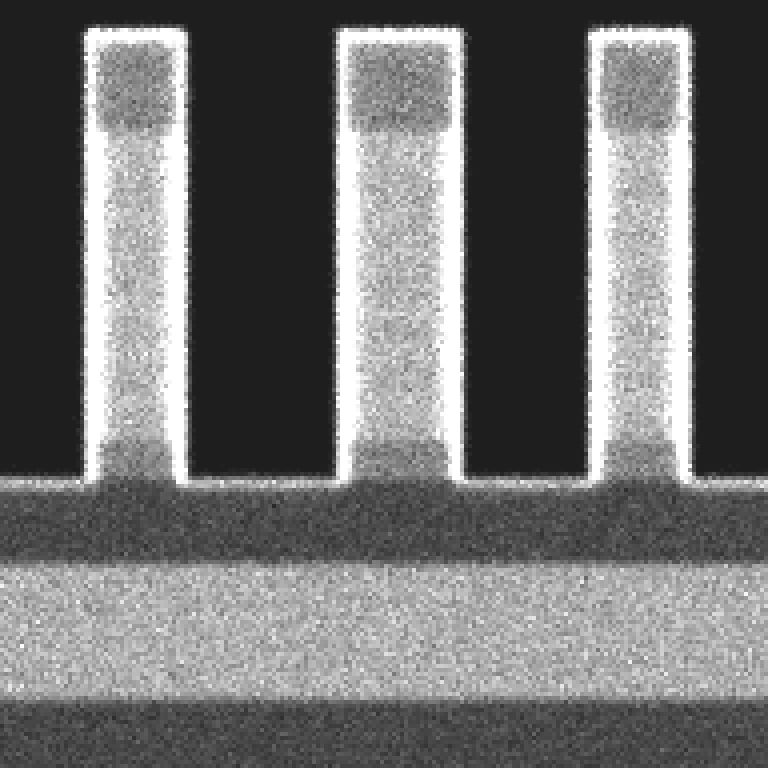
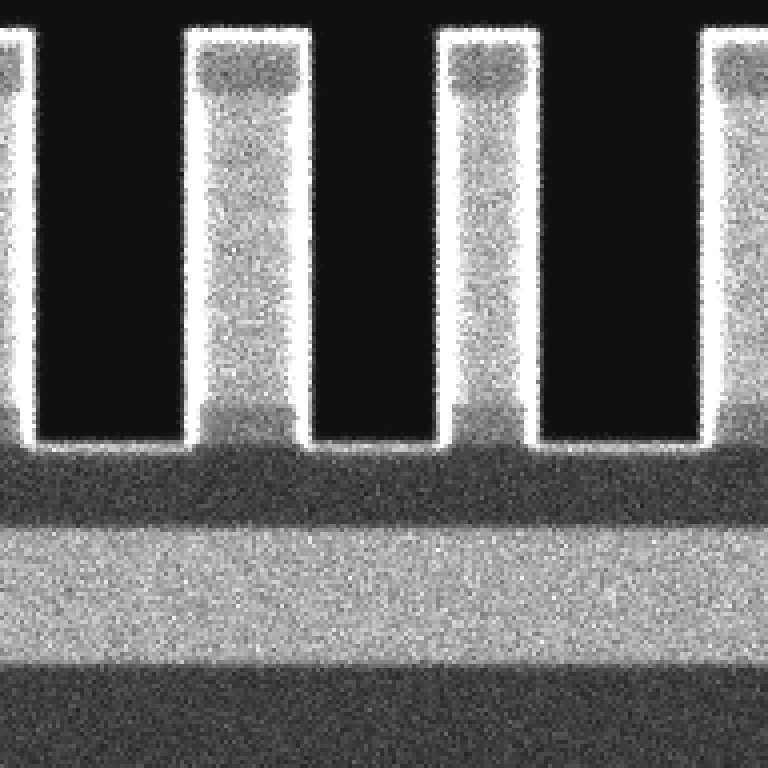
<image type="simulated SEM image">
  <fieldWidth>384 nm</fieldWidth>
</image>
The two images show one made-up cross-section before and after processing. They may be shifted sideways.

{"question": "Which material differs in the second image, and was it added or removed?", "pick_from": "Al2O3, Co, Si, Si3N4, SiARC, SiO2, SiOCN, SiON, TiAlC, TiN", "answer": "TiN, removed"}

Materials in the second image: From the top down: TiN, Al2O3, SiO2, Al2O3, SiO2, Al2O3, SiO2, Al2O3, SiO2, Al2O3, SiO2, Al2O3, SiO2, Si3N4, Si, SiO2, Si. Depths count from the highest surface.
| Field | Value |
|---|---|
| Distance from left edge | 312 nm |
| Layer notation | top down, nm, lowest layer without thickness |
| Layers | empty 206, Si 42, SiO2 68, Si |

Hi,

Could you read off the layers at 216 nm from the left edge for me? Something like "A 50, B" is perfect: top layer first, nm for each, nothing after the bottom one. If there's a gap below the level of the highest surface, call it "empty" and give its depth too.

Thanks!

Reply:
empty 206, Si 42, SiO2 68, Si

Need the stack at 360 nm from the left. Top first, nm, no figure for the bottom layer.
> TiN 32, Al2O3 22, SiO2 12, Al2O3 12, SiO2 12, Al2O3 12, SiO2 12, Al2O3 12, SiO2 12, Al2O3 12, SiO2 12, Al2O3 12, SiO2 12, Si3N4 20, Si 42, SiO2 68, Si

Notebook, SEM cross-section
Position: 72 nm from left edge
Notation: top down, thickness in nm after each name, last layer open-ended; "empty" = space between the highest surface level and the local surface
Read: empty 206, Si 42, SiO2 68, Si